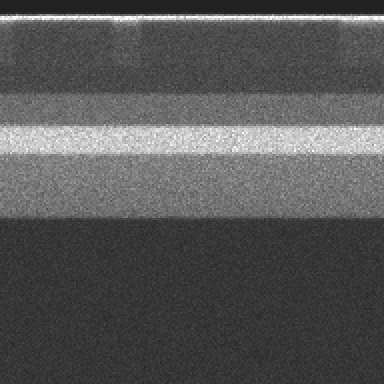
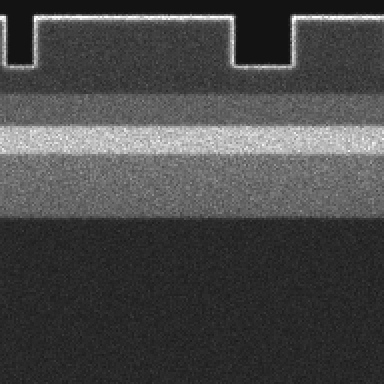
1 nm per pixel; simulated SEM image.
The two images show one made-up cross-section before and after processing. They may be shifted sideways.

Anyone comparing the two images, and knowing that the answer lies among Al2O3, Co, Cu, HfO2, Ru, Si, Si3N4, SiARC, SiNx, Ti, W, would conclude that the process removed SiARC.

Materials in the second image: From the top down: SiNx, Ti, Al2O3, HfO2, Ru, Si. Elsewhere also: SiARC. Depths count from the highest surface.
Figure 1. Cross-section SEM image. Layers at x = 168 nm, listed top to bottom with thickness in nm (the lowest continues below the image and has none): SiNx 50, Ti 28, Al2O3 32, HfO2 28, Ru 64, Si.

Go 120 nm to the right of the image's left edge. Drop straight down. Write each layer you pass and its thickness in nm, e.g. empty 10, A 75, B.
SiNx 50, Ti 28, Al2O3 32, HfO2 28, Ru 64, Si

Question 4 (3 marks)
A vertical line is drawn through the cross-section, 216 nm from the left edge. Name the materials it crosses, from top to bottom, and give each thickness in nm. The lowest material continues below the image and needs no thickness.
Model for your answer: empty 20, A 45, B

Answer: SiNx 50, Ti 28, Al2O3 32, HfO2 28, Ru 64, Si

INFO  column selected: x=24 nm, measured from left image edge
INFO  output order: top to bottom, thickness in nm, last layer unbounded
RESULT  empty 50, Ti 28, Al2O3 32, HfO2 28, Ru 64, Si